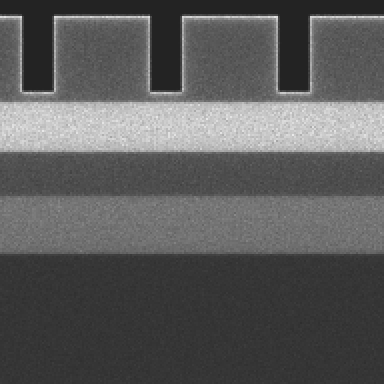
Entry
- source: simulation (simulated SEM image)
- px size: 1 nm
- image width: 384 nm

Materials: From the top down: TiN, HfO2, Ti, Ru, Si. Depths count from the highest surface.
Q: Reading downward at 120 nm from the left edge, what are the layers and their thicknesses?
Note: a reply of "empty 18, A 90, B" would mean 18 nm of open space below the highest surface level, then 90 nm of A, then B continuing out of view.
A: TiN 86, HfO2 50, Ti 44, Ru 58, Si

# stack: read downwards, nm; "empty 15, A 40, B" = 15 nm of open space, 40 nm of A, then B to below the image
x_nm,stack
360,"TiN 86, HfO2 50, Ti 44, Ru 58, Si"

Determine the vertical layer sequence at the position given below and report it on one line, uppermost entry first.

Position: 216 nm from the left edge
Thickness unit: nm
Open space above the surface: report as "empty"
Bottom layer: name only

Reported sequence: TiN 86, HfO2 50, Ti 44, Ru 58, Si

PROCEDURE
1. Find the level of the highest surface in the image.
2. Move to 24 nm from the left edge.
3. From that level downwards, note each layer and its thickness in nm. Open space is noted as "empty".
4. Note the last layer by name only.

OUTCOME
empty 76, TiN 10, HfO2 50, Ti 44, Ru 58, Si